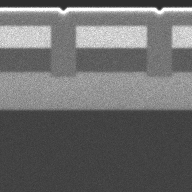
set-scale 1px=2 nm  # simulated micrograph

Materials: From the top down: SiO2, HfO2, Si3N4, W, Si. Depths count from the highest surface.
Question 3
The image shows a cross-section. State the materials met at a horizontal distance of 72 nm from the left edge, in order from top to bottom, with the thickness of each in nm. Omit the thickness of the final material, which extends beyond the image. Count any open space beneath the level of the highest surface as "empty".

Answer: SiO2 36, HfO2 44, Si3N4 48, W 76, Si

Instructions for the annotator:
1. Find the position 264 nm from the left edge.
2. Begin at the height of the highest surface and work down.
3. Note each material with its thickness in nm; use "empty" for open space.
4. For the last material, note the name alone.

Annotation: SiO2 36, HfO2 44, Si3N4 48, W 76, Si